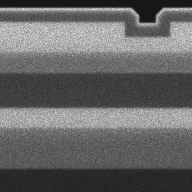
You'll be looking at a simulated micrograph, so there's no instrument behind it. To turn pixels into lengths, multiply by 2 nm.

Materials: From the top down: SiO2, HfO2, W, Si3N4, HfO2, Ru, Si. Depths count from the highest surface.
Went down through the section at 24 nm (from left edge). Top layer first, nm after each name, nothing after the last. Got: SiO2 28, HfO2 60, W 42, Si3N4 70, HfO2 40, Ru 82, Si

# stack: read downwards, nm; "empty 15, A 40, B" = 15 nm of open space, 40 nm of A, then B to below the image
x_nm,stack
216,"SiO2 28, HfO2 60, W 42, Si3N4 70, HfO2 40, Ru 82, Si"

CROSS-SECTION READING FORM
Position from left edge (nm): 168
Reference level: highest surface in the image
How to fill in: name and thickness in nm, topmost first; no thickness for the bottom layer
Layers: SiO2 28, HfO2 60, W 42, Si3N4 70, HfO2 40, Ru 82, Si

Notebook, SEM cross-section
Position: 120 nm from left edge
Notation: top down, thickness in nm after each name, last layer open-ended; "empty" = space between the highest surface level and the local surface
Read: SiO2 28, HfO2 60, W 42, Si3N4 70, HfO2 40, Ru 82, Si